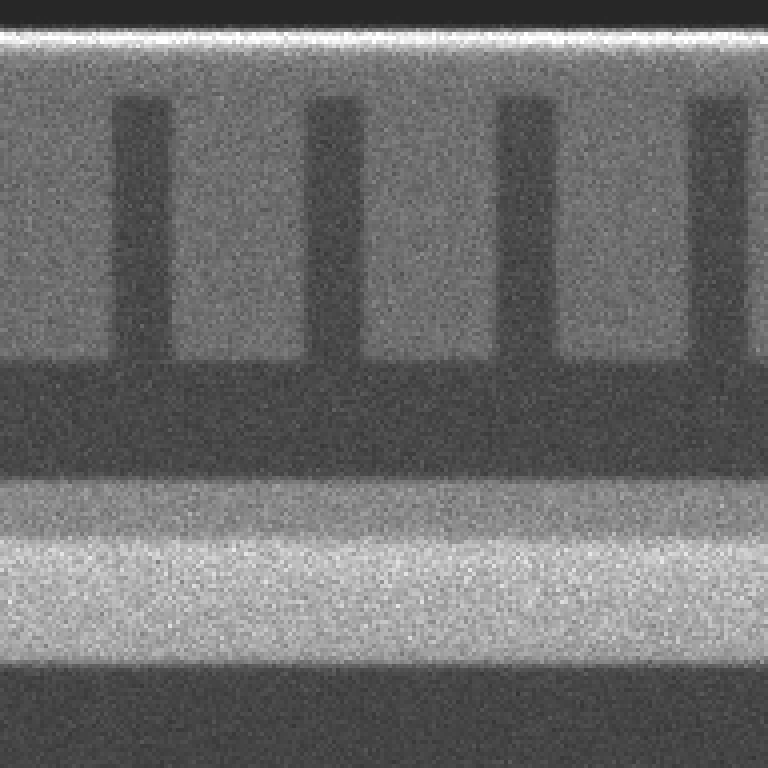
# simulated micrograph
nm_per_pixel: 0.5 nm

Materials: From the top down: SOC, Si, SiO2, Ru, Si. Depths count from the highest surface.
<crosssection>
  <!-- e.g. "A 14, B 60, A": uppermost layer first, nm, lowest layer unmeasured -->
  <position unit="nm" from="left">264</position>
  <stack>SOC 32, Si 192, SiO2 30, Ru 62, Si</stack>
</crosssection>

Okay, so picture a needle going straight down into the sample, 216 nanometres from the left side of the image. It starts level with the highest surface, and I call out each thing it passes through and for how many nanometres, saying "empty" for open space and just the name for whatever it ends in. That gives SOC 164, Si 60, SiO2 30, Ru 62, Si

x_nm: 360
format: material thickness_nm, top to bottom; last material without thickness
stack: SOC 32, Si 192, SiO2 30, Ru 62, Si